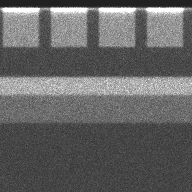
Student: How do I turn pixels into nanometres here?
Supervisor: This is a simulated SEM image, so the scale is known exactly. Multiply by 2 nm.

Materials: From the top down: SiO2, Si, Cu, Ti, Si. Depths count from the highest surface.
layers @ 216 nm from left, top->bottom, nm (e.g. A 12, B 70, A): SiO2 78, Si 60, Cu 36, Ti 56, Si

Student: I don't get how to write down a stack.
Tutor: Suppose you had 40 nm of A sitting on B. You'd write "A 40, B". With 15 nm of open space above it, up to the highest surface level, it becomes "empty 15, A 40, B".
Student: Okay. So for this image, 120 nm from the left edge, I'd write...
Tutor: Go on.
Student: SiO2 78, Si 60, Cu 36, Ti 56, Si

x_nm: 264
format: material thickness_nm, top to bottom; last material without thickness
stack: SiO2 78, Si 60, Cu 36, Ti 56, Si